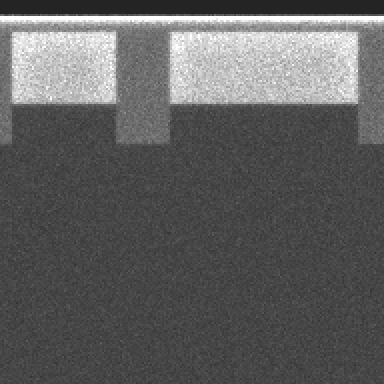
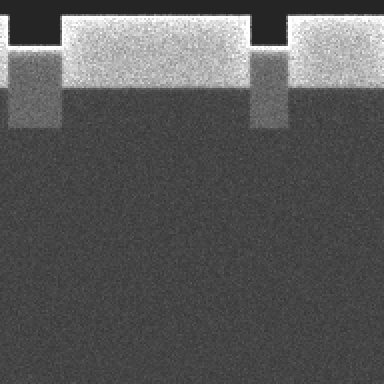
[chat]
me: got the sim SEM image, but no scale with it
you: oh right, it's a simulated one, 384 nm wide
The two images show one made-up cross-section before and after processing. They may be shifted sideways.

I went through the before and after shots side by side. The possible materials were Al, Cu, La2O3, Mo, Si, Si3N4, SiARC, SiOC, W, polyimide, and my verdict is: removed, SiARC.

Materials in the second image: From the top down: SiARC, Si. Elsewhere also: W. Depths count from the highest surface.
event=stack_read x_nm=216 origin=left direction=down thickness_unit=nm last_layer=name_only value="W 72, Si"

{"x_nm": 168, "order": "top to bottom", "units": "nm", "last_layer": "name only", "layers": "W 72, Si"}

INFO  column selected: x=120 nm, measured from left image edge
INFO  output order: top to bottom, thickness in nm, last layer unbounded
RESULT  W 72, Si